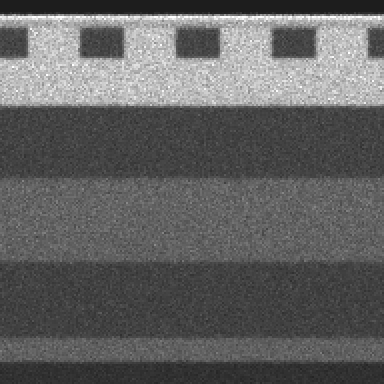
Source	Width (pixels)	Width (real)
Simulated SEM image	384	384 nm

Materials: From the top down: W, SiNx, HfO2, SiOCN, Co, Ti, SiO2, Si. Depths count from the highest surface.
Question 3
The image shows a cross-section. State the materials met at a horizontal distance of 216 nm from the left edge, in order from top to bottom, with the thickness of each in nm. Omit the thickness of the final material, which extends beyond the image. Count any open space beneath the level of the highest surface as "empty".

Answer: W 12, SiNx 30, HfO2 48, SiOCN 72, Co 84, Ti 76, SiO2 24, Si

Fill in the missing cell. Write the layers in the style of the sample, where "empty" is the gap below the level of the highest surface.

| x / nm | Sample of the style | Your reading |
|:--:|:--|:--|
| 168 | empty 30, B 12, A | W 12, HfO2 78, SiOCN 72, Co 84, Ti 76, SiO2 24, Si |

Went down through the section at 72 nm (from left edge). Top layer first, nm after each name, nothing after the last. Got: W 12, HfO2 78, SiOCN 72, Co 84, Ti 76, SiO2 24, Si